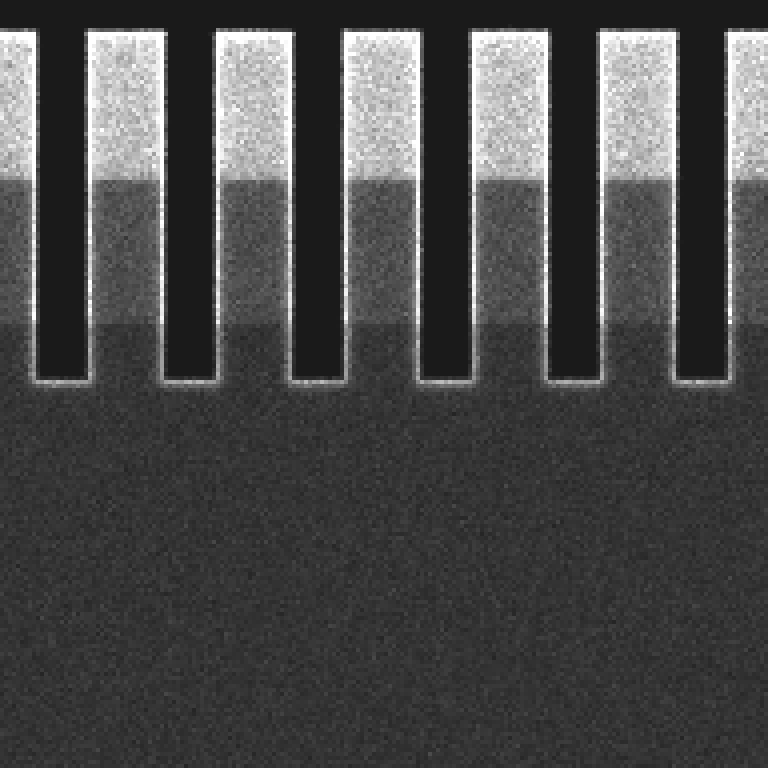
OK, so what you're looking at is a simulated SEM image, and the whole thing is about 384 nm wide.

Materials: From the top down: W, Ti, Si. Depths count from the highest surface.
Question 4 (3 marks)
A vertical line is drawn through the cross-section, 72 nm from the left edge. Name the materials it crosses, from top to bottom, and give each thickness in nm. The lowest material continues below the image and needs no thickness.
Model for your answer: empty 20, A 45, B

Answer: W 74, Ti 72, Si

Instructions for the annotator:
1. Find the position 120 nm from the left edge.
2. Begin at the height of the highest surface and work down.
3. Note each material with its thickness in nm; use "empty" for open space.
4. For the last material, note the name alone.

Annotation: W 74, Ti 72, Si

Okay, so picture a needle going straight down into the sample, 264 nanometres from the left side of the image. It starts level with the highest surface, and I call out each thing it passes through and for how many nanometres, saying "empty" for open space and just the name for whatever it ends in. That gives W 74, Ti 72, Si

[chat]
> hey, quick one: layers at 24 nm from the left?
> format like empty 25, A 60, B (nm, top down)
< empty 174, Si